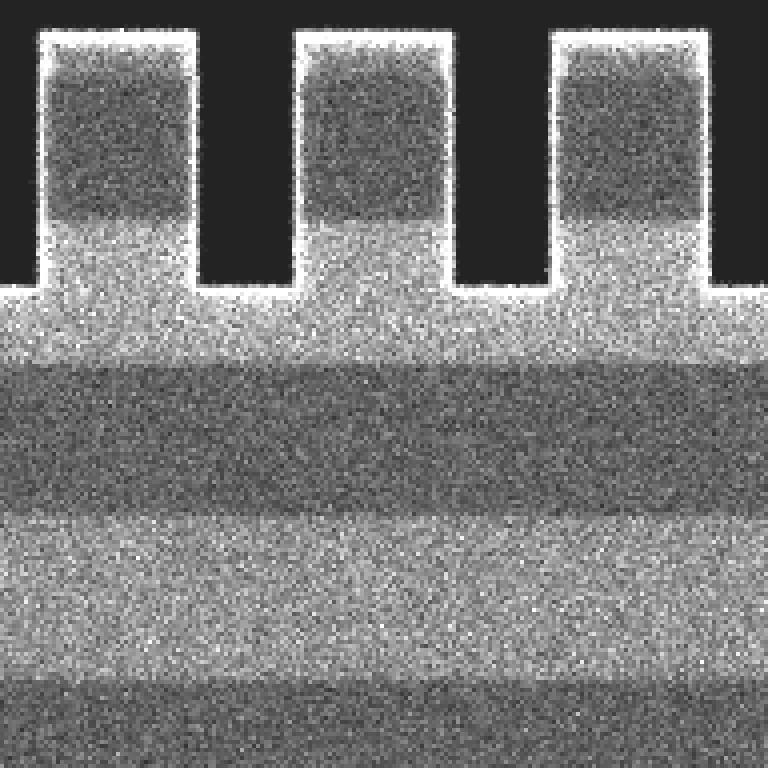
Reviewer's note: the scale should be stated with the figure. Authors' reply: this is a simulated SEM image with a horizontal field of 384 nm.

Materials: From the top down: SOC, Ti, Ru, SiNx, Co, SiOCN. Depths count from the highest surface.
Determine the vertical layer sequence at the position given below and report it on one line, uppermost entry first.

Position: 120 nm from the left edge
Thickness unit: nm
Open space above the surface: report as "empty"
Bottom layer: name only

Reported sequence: empty 128, Ru 38, SiNx 76, Co 82, SiOCN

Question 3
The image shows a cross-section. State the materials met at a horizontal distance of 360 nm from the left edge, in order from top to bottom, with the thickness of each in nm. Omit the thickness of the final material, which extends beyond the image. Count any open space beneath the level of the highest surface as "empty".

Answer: empty 128, Ru 38, SiNx 76, Co 82, SiOCN